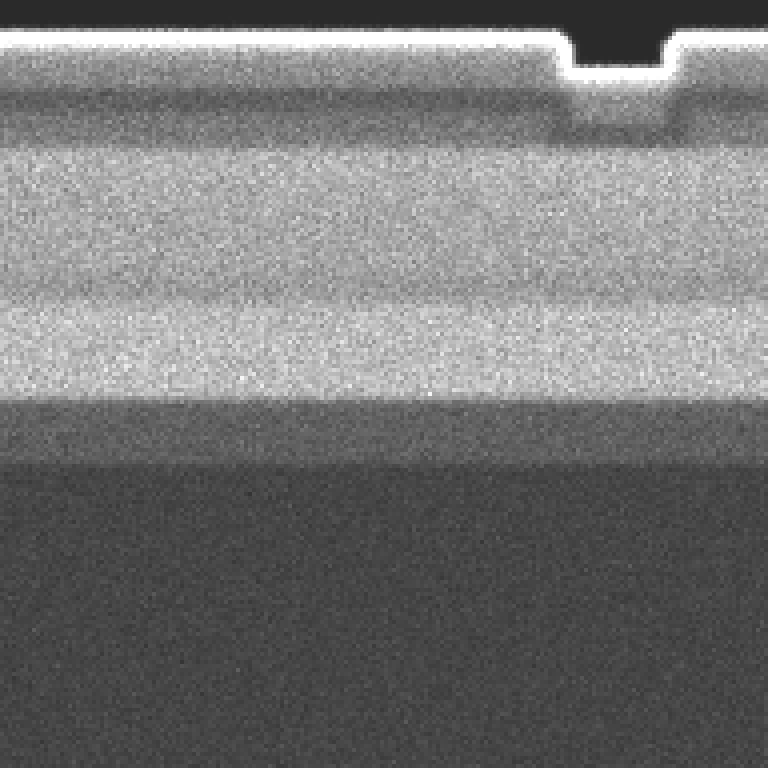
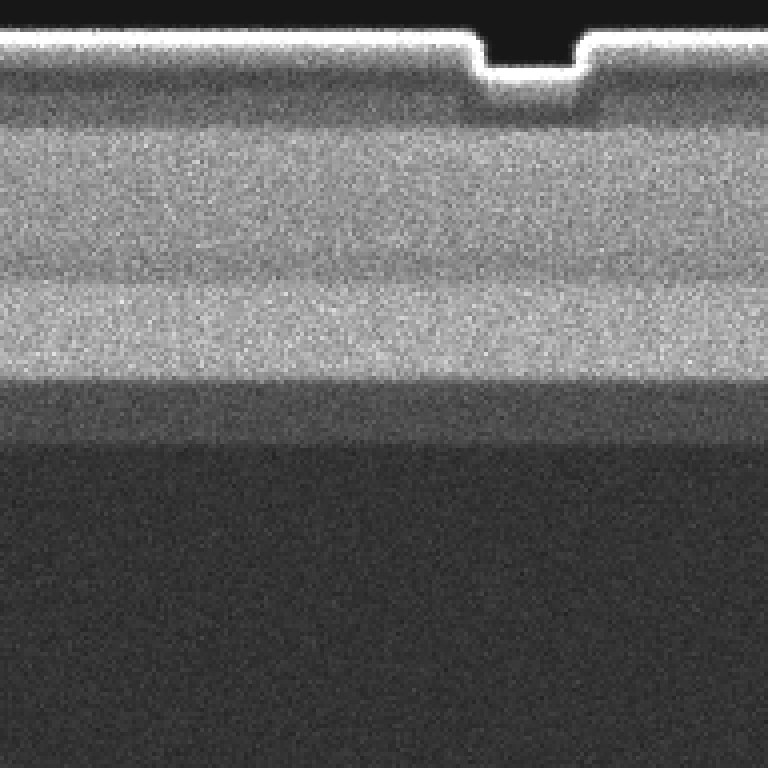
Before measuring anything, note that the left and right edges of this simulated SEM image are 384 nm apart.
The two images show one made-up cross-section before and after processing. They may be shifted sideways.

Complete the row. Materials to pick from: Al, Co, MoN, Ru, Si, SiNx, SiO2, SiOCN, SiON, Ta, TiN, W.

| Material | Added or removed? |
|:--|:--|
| SiO2 | removed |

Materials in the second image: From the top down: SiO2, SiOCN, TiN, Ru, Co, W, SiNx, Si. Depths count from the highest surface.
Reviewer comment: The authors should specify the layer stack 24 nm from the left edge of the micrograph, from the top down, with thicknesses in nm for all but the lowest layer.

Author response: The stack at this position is SiO2 18, SiOCN 12, TiN 18, Ru 62, Co 16, W 48, SiNx 32, Si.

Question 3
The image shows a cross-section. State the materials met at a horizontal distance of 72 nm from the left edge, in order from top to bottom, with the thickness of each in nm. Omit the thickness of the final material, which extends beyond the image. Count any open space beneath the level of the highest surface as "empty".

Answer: SiO2 18, SiOCN 12, TiN 18, Ru 62, Co 16, W 48, SiNx 32, Si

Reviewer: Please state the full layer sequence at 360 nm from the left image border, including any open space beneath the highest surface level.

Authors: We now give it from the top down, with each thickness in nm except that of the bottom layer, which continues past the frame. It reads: SiO2 18, SiOCN 12, TiN 18, Ru 62, Co 16, W 48, SiNx 32, Si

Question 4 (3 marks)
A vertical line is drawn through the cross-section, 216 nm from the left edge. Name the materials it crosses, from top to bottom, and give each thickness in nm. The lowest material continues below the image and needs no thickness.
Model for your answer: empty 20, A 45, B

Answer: SiO2 18, SiOCN 12, TiN 18, Ru 62, Co 16, W 48, SiNx 32, Si